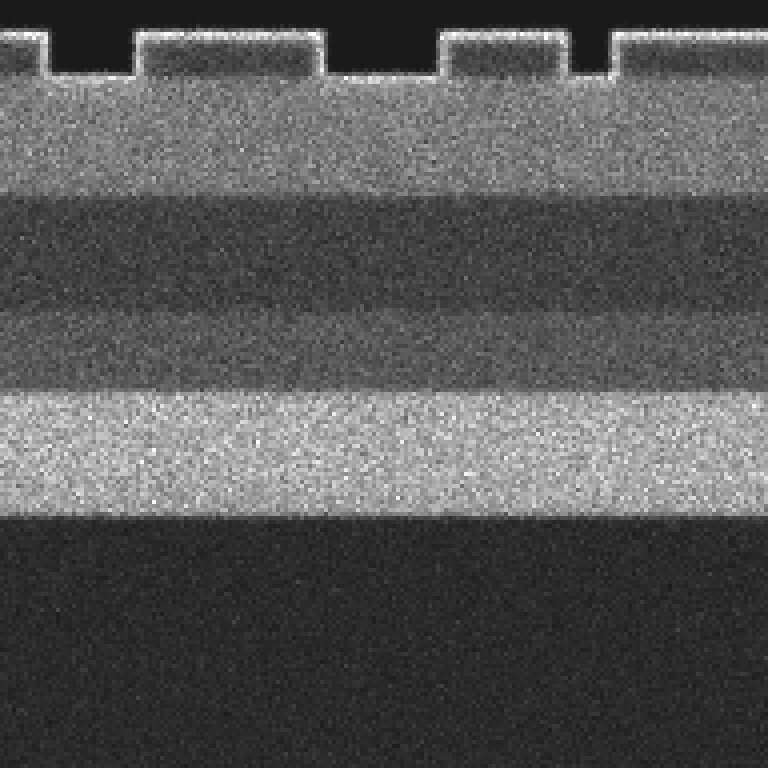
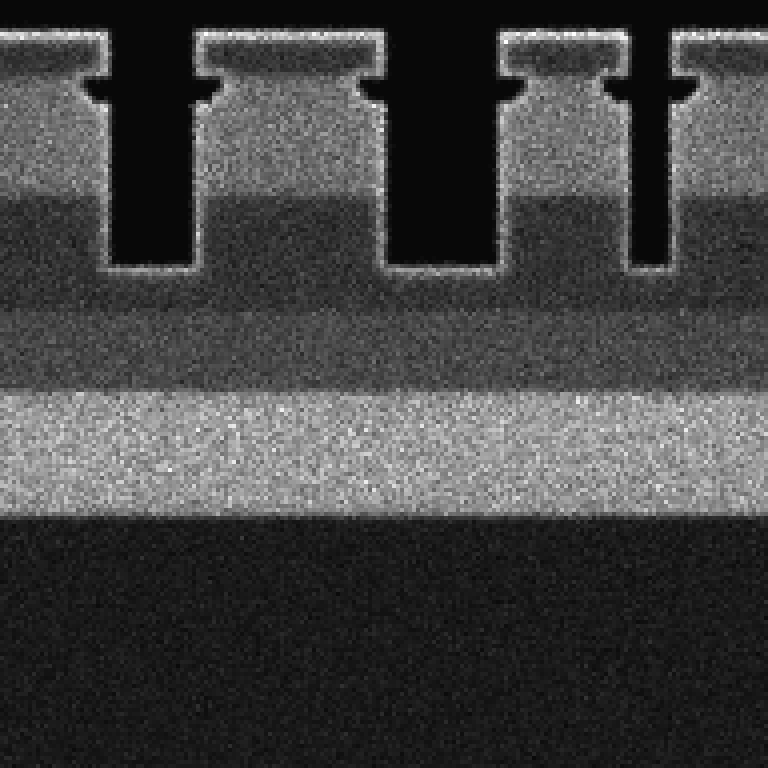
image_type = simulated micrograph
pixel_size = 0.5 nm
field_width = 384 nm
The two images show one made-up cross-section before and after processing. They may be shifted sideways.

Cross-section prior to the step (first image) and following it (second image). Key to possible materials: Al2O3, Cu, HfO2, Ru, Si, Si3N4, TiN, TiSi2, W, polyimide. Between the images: TiN and W was removed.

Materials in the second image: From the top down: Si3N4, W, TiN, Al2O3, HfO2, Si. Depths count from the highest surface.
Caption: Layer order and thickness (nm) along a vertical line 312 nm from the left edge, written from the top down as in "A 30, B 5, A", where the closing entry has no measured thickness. Si3N4 22, empty 14, W 46, TiN 58, Al2O3 40, HfO2 62, Si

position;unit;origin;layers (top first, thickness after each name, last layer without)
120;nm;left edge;Si3N4 22, W 60, TiN 58, Al2O3 40, HfO2 62, Si